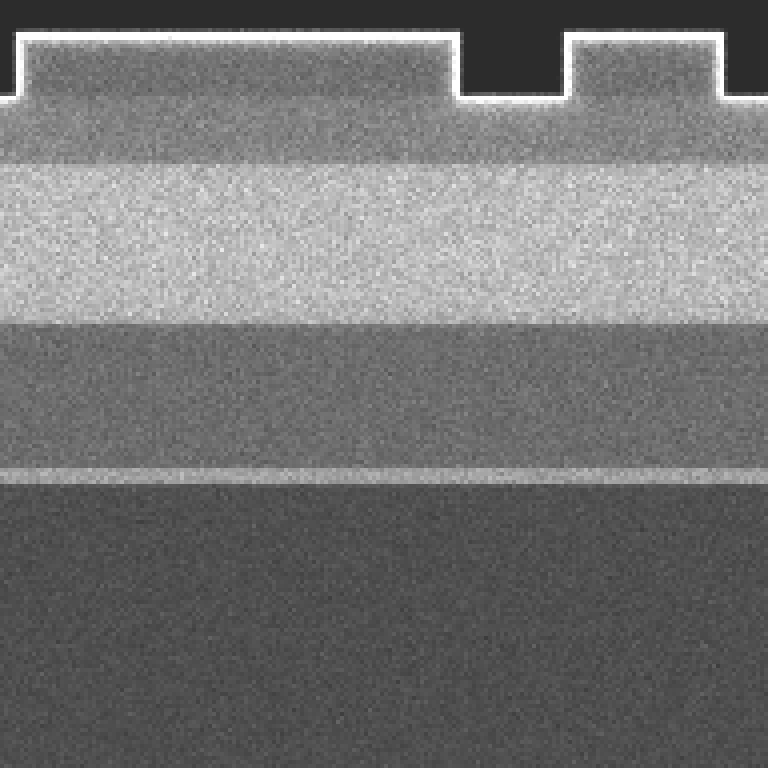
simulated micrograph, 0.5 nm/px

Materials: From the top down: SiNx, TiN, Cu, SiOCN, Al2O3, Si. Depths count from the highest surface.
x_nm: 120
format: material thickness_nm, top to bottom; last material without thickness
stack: SiNx 32, TiN 34, Cu 80, SiOCN 72, Al2O3 8, Si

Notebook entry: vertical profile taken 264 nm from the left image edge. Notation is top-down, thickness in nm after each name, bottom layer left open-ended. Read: empty 32, TiN 34, Cu 80, SiOCN 72, Al2O3 8, Si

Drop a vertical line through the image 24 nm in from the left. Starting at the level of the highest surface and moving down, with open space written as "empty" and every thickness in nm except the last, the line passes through SiNx 32, TiN 34, Cu 80, SiOCN 72, Al2O3 8, Si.